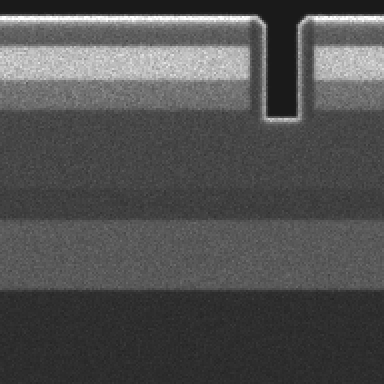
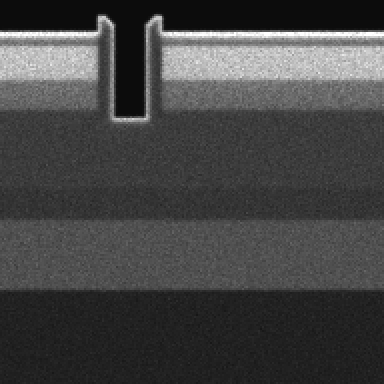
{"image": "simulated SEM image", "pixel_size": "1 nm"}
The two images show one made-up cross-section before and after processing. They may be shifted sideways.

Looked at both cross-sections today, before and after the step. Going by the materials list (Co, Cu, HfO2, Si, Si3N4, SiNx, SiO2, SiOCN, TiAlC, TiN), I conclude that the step removed SiO2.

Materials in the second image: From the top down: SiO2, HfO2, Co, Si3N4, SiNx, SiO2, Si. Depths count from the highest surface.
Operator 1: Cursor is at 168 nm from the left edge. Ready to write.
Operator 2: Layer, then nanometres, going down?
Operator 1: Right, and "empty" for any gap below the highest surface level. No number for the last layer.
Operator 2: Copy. empty 16, SiO2 14, HfO2 34, Co 30, Si3N4 78, SiNx 32, SiO2 70, Si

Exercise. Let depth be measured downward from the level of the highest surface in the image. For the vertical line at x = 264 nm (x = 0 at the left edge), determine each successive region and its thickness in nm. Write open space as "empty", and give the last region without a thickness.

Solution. empty 16, SiO2 14, HfO2 34, Co 30, Si3N4 78, SiNx 32, SiO2 70, Si